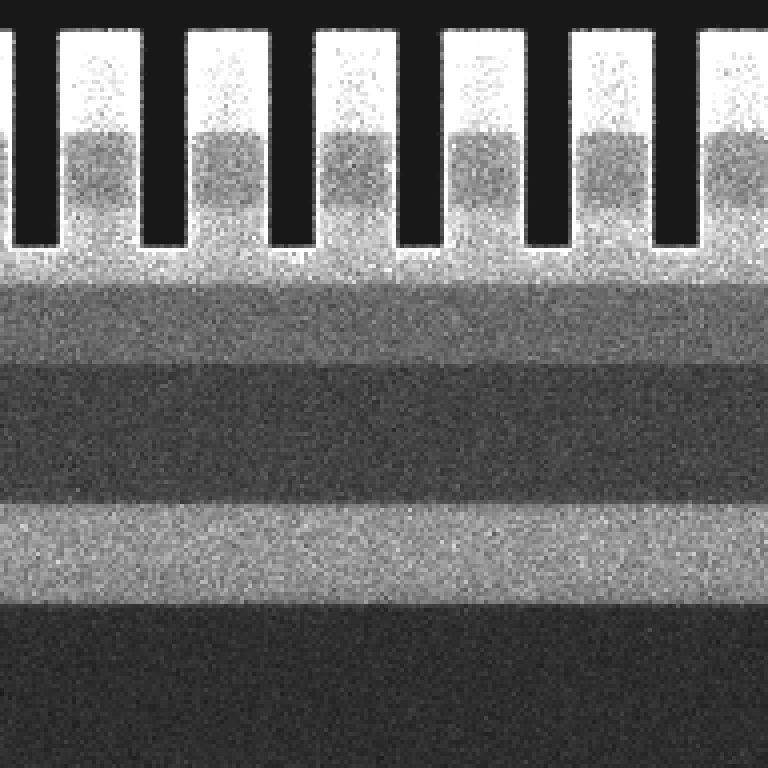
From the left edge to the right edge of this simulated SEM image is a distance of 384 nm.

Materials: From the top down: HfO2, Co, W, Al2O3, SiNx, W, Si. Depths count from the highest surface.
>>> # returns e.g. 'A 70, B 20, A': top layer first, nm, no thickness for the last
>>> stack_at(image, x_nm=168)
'HfO2 50, Co 38, W 38, Al2O3 40, SiNx 70, W 50, Si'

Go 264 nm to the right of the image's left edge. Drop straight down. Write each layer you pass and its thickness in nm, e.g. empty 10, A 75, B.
empty 108, W 18, Al2O3 40, SiNx 70, W 50, Si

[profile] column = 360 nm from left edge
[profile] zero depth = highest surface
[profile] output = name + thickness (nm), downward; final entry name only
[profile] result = HfO2 50, Co 38, W 38, Al2O3 40, SiNx 70, W 50, Si